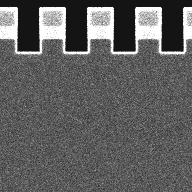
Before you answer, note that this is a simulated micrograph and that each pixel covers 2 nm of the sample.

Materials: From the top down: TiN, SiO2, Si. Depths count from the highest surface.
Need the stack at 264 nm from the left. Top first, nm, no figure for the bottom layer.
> empty 88, Si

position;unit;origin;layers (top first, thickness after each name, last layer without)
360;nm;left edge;empty 88, Si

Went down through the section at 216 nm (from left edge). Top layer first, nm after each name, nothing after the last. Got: TiN 36, SiO2 26, Si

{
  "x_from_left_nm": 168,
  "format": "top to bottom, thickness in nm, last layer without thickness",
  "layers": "empty 88, Si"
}